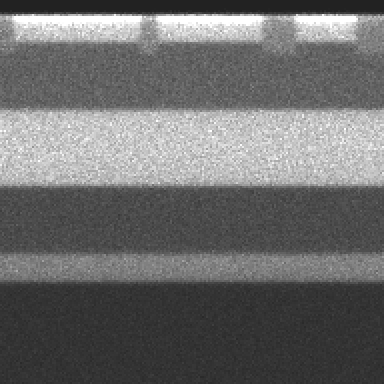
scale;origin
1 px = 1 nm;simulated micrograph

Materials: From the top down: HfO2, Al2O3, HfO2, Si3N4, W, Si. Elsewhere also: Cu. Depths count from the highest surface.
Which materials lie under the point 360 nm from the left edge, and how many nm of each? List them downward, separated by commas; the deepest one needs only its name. Cu 38, Al2O3 56, HfO2 76, Si3N4 68, W 28, Si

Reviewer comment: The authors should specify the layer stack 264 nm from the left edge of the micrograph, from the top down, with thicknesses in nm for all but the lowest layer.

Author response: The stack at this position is Cu 38, Al2O3 56, HfO2 76, Si3N4 68, W 28, Si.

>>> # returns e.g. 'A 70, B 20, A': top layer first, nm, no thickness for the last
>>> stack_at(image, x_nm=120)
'HfO2 26, Al2O3 68, HfO2 76, Si3N4 68, W 28, Si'